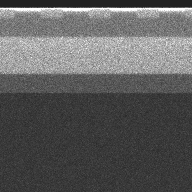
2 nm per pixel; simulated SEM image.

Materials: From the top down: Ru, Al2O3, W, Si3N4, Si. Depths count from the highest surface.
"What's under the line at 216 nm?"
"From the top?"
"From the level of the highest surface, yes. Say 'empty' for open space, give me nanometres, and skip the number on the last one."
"Ru 20, Al2O3 38, W 74, Si3N4 38, Si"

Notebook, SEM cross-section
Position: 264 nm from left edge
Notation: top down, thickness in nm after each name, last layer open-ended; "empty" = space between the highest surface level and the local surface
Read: Al2O3 58, W 74, Si3N4 38, Si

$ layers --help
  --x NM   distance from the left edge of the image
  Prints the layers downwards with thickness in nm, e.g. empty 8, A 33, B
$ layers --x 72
Al2O3 58, W 74, Si3N4 38, Si